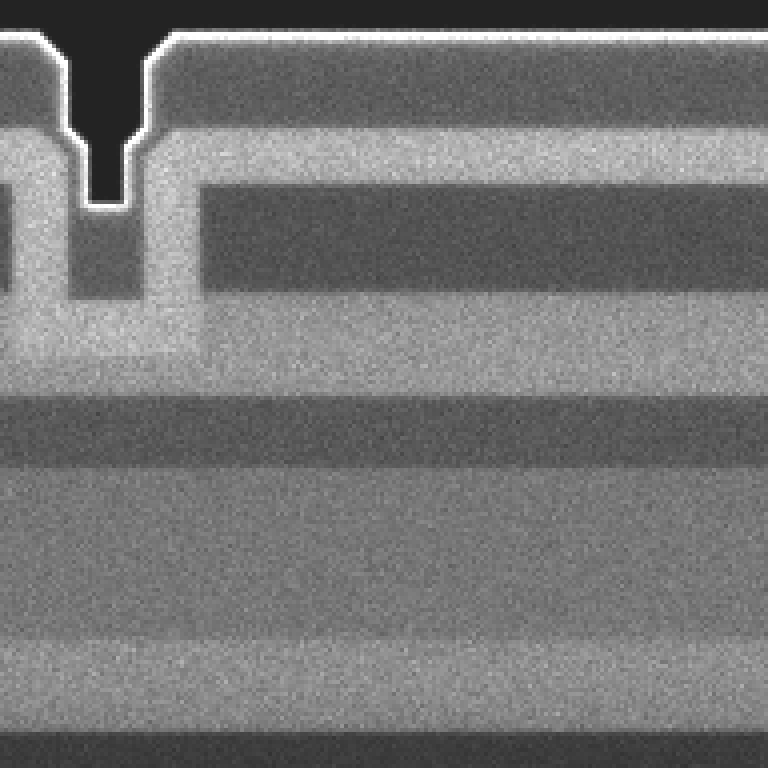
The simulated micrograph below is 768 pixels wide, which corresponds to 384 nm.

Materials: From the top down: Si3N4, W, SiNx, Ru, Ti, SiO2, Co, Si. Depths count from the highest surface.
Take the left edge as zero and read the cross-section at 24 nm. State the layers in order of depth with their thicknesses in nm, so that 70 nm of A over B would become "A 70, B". empty 6, Si3N4 48, W 108, Ru 20, Ti 36, SiO2 86, Co 46, Si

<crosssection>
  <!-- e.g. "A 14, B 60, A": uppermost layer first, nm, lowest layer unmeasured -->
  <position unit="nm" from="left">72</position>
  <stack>empty 14, Si3N4 48, W 100, Ru 20, Ti 36, SiO2 86, Co 46, Si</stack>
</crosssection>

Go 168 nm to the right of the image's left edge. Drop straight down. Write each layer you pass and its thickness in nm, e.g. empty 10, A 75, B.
Si3N4 48, W 28, SiNx 54, Ru 52, Ti 36, SiO2 86, Co 46, Si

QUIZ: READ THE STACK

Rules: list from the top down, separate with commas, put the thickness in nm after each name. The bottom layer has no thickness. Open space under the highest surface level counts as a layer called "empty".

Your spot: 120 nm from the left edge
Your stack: Si3N4 48, W 28, SiNx 54, Ru 52, Ti 36, SiO2 86, Co 46, Si